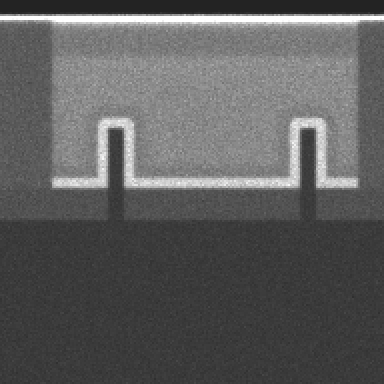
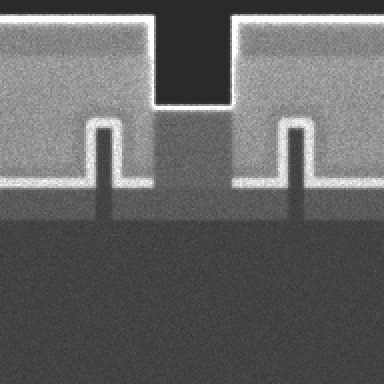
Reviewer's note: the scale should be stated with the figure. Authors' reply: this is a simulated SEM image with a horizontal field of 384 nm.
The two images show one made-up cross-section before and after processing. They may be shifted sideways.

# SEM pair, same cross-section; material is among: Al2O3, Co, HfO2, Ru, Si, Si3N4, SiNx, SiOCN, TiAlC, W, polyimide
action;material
removed;Si3N4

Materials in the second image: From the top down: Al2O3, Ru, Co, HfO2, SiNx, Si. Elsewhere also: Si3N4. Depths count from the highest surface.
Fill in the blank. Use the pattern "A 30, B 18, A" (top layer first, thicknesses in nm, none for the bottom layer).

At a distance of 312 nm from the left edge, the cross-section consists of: Al2O3 40, Ru 50, Co 16, HfO2 66, SiNx 32, Si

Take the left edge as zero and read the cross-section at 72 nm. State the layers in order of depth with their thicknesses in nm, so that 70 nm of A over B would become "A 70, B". Al2O3 40, Ru 110, Co 12, HfO2 10, SiNx 32, Si